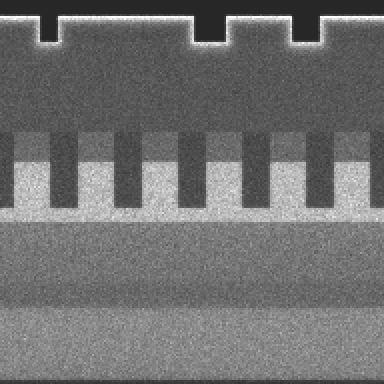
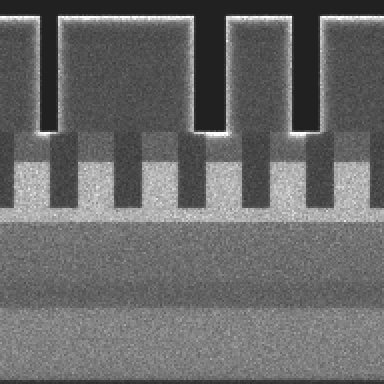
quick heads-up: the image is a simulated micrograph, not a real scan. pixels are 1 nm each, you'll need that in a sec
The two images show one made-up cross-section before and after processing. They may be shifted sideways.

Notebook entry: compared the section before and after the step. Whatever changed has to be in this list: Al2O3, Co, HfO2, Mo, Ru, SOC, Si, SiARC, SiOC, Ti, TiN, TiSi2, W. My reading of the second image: SOC removed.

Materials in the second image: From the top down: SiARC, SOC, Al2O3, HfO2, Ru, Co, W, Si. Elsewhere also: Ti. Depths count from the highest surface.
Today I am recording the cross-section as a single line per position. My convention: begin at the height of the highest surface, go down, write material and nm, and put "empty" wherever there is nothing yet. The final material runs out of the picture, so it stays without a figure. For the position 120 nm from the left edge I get SiARC 26, SOC 90, Ti 76, HfO2 14, Ru 60, Co 26, W 72, Si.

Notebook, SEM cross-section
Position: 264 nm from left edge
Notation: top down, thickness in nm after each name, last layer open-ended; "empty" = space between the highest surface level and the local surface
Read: SiARC 26, SOC 90, Ti 76, HfO2 14, Ru 60, Co 26, W 72, Si